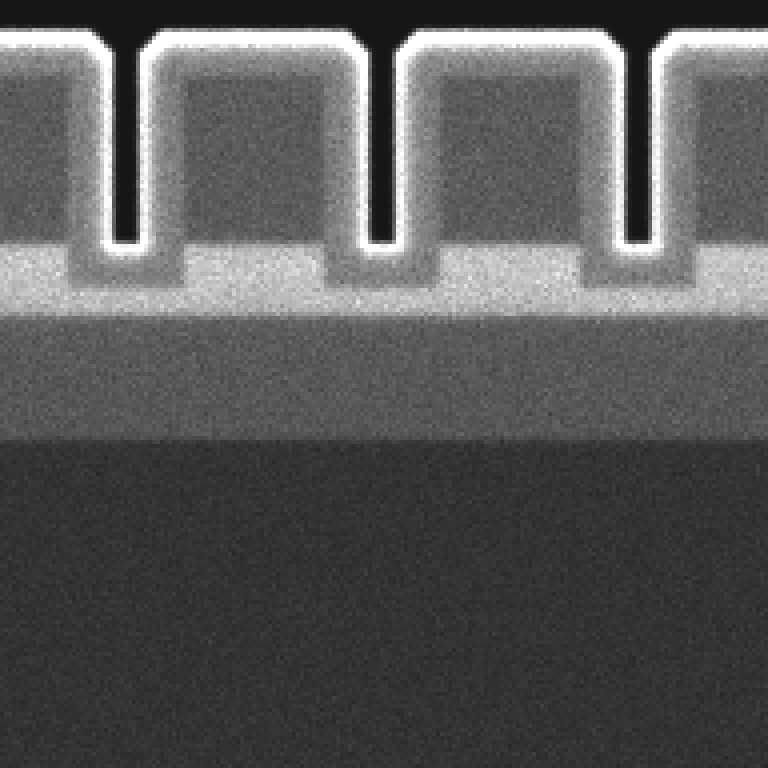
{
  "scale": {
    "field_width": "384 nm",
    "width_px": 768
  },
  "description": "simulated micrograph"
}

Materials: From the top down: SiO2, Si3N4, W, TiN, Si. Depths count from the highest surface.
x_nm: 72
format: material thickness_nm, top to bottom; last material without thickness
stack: empty 8, SiO2 120, W 14, TiN 62, Si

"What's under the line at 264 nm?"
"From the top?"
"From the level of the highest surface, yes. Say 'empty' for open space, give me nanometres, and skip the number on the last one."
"SiO2 22, Si3N4 84, W 36, TiN 62, Si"